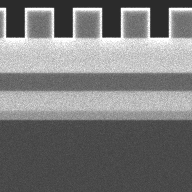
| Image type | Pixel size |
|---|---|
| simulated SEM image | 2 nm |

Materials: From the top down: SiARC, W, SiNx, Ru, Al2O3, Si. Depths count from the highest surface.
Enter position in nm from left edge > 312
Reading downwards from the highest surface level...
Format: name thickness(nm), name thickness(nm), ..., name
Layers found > empty 60, W 70, SiNx 36, Ru 40, Al2O3 18, Si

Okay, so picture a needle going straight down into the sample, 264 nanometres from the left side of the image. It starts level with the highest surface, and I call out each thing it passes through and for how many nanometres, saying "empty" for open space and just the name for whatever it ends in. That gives SiARC 60, W 70, SiNx 36, Ru 40, Al2O3 18, Si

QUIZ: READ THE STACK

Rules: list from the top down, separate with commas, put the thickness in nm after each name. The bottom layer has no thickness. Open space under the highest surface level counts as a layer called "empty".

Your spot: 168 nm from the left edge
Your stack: SiARC 60, W 70, SiNx 36, Ru 40, Al2O3 18, Si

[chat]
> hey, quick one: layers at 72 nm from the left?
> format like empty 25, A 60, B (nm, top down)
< SiARC 60, W 70, SiNx 36, Ru 40, Al2O3 18, Si